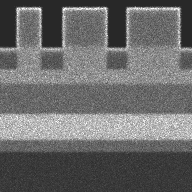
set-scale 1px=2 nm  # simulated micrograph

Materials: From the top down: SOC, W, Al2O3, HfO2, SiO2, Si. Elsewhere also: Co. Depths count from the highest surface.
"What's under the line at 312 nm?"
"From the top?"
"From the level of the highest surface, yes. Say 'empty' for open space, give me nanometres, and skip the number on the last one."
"Co 76, W 76, Al2O3 60, HfO2 52, SiO2 24, Si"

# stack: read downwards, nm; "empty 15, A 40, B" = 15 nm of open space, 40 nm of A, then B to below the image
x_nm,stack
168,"Co 76, W 76, Al2O3 60, HfO2 52, SiO2 24, Si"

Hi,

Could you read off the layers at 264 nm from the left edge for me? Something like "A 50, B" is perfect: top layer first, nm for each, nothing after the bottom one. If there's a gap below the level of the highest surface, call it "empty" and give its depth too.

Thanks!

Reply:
Co 76, W 76, Al2O3 60, HfO2 52, SiO2 24, Si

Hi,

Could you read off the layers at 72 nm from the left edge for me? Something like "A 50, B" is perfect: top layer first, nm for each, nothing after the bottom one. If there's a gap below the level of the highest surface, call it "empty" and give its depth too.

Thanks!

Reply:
Co 76, W 76, Al2O3 60, HfO2 52, SiO2 24, Si